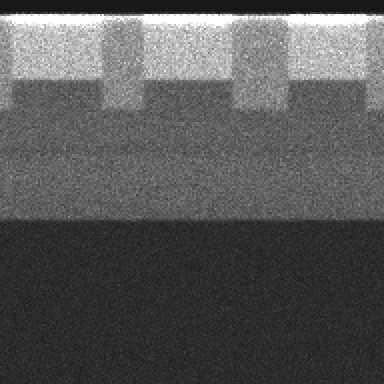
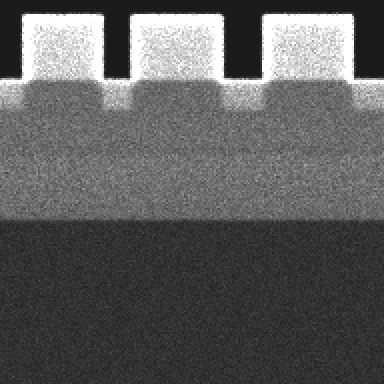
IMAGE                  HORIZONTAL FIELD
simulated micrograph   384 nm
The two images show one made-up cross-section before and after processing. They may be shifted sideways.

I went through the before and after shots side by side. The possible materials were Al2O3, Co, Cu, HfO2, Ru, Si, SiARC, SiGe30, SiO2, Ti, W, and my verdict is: removed, W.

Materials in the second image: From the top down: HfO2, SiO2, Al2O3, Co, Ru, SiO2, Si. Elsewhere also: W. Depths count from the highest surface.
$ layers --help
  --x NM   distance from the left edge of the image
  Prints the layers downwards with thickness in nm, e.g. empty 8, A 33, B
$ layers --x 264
HfO2 64, SiO2 40, Al2O3 26, Co 10, Ru 50, SiO2 14, Si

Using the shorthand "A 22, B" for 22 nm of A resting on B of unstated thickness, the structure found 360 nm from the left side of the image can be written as empty 64, W 30, SiO2 10, Al2O3 26, Co 10, Ru 50, SiO2 14, Si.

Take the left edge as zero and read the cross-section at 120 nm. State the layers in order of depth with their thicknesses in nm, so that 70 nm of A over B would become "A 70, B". empty 64, W 30, SiO2 10, Al2O3 26, Co 10, Ru 50, SiO2 14, Si